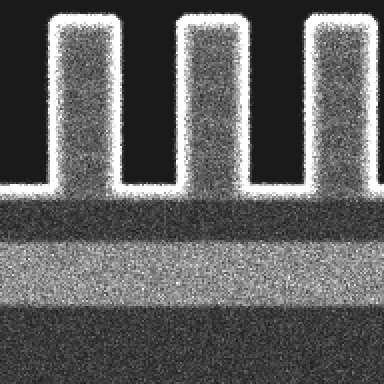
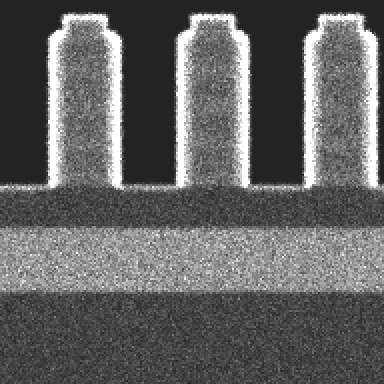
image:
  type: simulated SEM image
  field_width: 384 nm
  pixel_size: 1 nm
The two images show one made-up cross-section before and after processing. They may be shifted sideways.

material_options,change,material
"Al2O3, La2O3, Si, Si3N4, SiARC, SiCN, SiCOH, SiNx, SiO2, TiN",removed,Al2O3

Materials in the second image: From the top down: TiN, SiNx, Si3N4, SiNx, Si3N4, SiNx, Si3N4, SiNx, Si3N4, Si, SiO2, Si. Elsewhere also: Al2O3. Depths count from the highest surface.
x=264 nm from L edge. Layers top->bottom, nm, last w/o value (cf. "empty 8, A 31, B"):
empty 170, Si 42, SiO2 64, Si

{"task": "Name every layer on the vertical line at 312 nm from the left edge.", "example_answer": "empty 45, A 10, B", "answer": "empty 16, Al2O3 154, Si 42, SiO2 64, Si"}